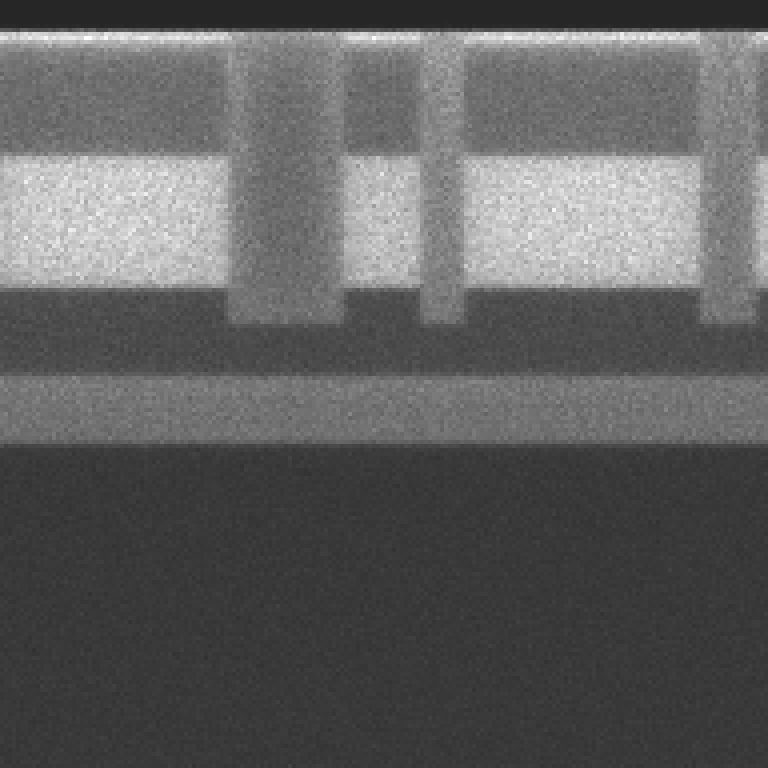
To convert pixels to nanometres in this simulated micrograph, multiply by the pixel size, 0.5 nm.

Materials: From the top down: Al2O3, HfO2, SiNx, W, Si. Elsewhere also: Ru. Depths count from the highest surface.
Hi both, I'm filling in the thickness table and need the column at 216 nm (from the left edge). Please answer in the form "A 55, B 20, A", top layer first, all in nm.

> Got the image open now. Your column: Ru 146, SiNx 26, W 34, Si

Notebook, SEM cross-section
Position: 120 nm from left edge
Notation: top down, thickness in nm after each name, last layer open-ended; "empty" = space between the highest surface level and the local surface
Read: Ru 146, SiNx 26, W 34, Si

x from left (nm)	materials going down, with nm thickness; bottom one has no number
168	Ru 146, SiNx 26, W 34, Si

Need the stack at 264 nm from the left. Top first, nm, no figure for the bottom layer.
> Al2O3 62, HfO2 66, SiNx 44, W 34, Si